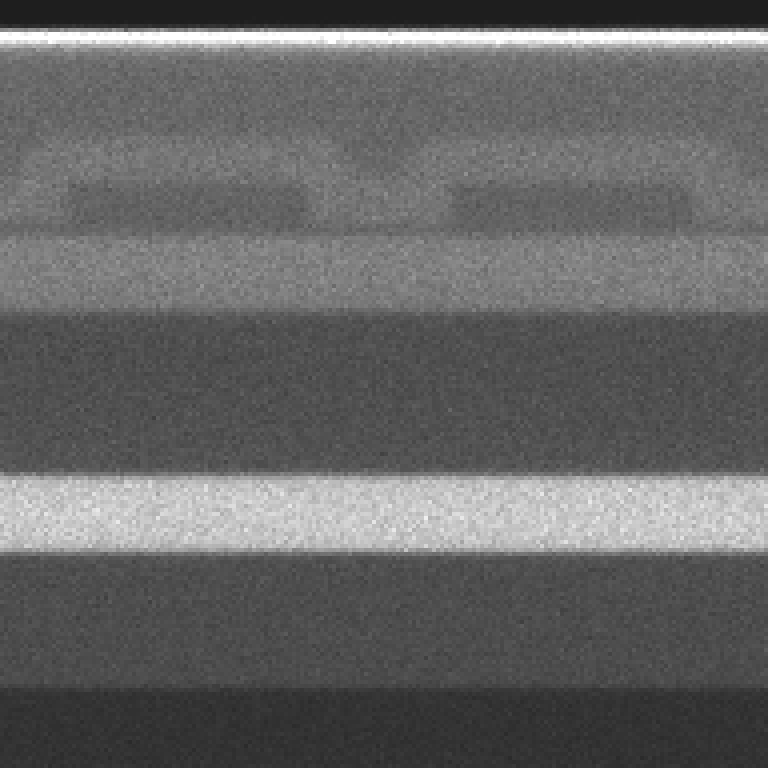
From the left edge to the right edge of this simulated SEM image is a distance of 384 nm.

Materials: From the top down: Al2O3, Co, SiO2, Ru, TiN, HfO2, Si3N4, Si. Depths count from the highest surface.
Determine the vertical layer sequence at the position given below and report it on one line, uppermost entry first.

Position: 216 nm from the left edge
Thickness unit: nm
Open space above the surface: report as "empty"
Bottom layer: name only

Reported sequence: Al2O3 52, Co 44, SiO2 6, Ru 38, TiN 82, HfO2 38, Si3N4 68, Si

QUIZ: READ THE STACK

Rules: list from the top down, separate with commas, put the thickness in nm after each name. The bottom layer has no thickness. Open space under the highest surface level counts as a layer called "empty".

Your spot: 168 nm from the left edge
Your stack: Al2O3 56, Co 40, SiO2 6, Ru 38, TiN 82, HfO2 38, Si3N4 68, Si